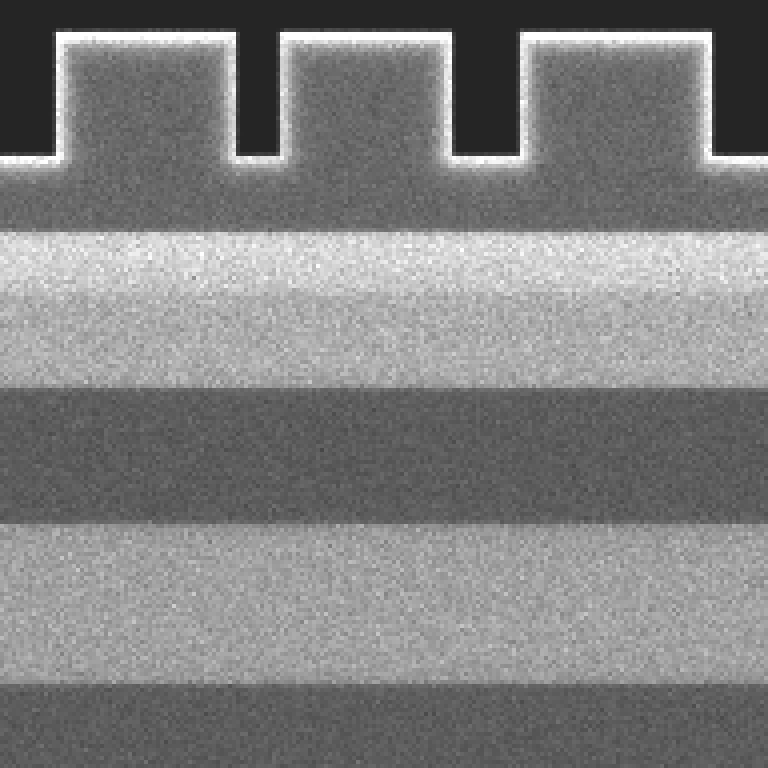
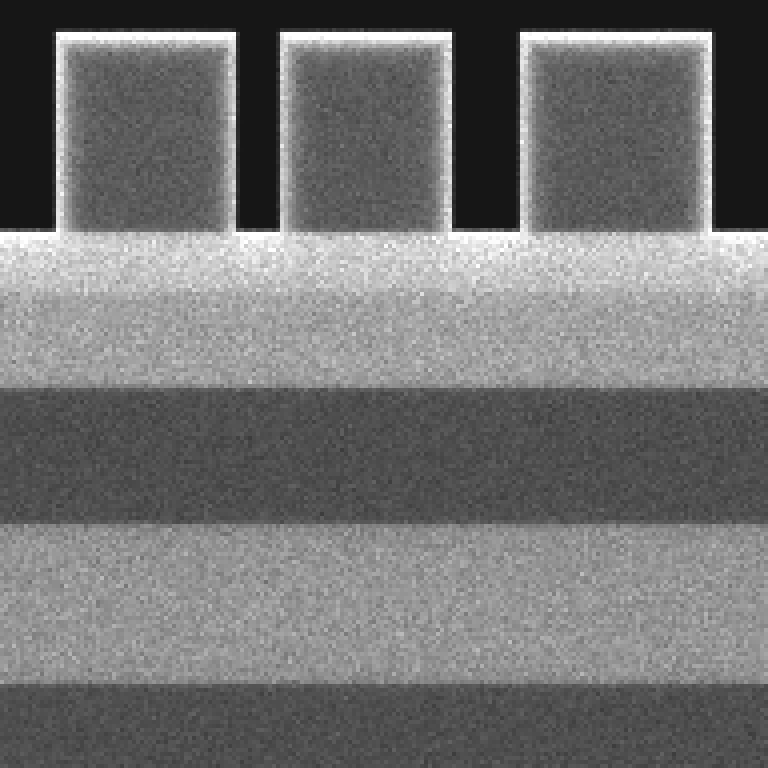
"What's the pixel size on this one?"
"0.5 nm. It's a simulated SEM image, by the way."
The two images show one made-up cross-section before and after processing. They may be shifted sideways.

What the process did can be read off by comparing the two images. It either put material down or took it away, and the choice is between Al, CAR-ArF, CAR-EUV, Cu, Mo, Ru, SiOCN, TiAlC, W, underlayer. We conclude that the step removed underlayer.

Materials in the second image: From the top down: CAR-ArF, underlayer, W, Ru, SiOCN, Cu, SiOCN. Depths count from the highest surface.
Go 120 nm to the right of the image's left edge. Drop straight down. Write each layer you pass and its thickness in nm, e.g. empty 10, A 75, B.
empty 100, W 30, Ru 48, SiOCN 68, Cu 80, SiOCN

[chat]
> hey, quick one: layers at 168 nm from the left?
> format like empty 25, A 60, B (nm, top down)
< CAR-ArF 62, underlayer 38, W 30, Ru 48, SiOCN 68, Cu 80, SiOCN